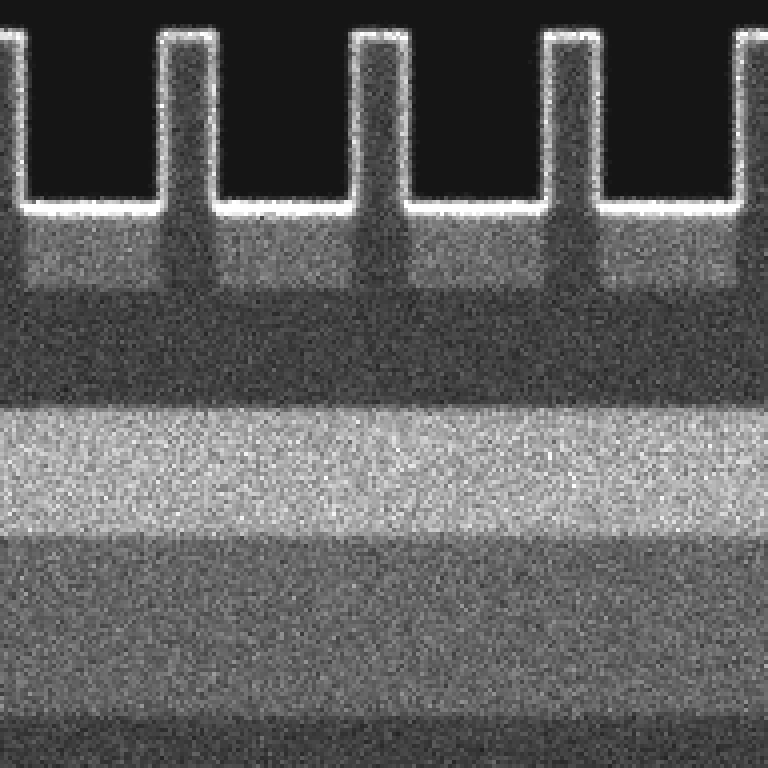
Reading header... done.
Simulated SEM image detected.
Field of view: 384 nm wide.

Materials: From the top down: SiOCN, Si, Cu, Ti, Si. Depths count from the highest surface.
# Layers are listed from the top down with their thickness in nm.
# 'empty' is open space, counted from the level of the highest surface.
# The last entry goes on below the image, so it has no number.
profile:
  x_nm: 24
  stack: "empty 86, SiOCN 42, Si 60, Cu 64, Ti 90, Si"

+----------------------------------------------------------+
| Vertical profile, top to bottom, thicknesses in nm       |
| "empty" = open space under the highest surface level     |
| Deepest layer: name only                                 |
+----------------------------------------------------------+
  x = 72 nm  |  empty 86, SiOCN 42, Si 60, Cu 64, Ti 90, Si